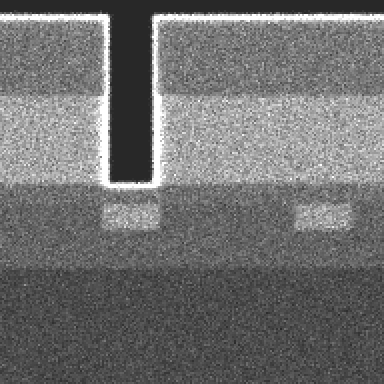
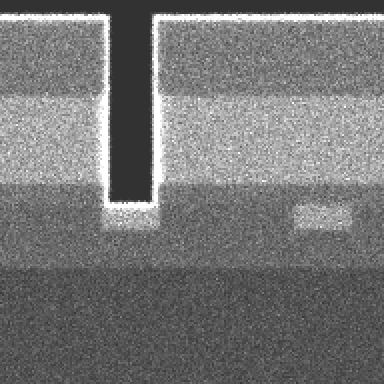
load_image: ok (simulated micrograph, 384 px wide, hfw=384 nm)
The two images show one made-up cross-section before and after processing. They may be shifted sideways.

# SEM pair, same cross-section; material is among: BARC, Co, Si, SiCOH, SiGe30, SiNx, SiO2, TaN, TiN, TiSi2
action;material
removed;SiNx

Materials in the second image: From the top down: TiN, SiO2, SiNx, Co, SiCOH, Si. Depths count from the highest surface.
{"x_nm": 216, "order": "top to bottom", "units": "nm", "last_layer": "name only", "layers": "TiN 80, SiO2 88, SiNx 20, SiCOH 64, Si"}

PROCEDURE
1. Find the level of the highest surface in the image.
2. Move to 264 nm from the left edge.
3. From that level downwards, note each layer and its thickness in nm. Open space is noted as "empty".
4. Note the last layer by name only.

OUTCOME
TiN 80, SiO2 88, SiNx 20, SiCOH 64, Si